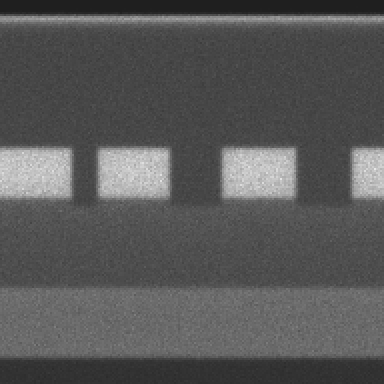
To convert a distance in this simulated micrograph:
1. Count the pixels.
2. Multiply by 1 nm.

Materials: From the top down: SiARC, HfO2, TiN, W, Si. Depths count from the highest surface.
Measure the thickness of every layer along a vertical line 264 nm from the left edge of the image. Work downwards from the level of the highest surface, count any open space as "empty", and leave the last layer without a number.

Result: SiARC 132, HfO2 50, TiN 90, W 70, Si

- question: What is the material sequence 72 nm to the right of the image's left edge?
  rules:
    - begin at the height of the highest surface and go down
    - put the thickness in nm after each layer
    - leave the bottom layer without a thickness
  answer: SiARC 190, TiN 82, W 70, Si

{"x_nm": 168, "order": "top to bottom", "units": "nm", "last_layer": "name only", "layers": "SiARC 132, HfO2 50, TiN 90, W 70, Si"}